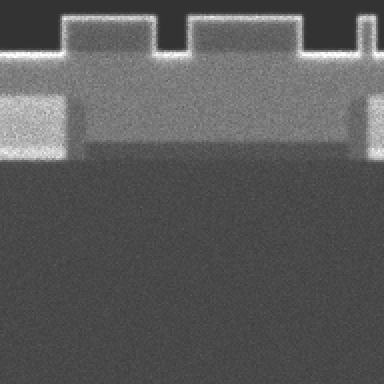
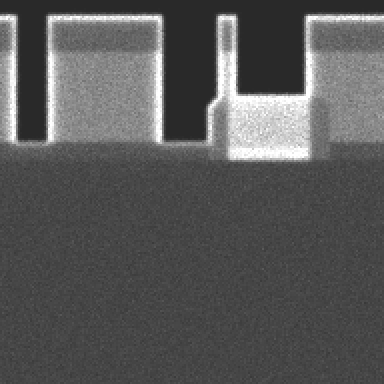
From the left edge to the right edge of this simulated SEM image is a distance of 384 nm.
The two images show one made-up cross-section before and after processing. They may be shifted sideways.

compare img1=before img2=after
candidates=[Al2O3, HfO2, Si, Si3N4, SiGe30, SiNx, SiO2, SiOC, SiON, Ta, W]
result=removed:SiO2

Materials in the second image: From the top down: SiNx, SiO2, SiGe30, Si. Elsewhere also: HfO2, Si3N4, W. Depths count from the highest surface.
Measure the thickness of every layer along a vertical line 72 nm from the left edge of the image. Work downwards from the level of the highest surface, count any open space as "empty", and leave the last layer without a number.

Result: SiNx 36, SiO2 90, SiGe30 18, Si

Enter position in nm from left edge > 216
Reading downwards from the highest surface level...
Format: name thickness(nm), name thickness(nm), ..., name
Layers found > empty 82, Si3N4 62, Si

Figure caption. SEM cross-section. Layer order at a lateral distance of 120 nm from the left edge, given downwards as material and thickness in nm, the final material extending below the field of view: SiNx 36, SiO2 90, SiGe30 18, Si